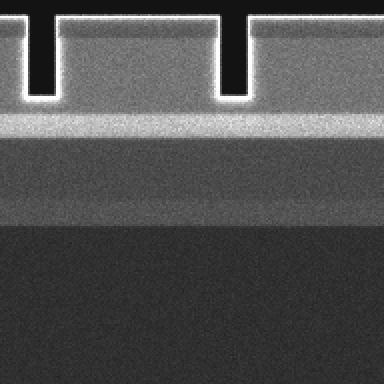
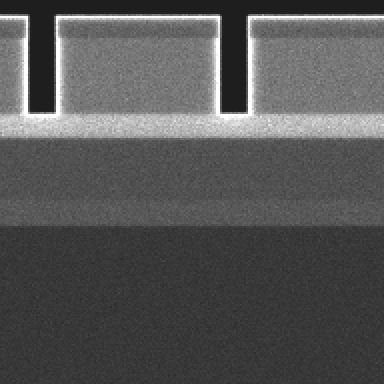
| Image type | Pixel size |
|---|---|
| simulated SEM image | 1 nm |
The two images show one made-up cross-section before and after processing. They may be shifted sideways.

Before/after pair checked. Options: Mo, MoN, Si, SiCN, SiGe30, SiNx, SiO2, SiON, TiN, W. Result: removed SiO2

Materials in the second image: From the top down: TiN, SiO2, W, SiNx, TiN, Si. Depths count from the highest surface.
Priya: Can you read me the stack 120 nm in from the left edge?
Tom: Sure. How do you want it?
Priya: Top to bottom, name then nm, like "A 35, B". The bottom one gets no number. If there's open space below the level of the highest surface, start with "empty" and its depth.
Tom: TiN 22, SiO2 76, W 24, SiNx 62, TiN 26, Si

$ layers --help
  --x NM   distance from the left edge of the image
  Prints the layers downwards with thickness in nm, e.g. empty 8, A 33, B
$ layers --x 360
TiN 22, SiO2 76, W 24, SiNx 62, TiN 26, Si